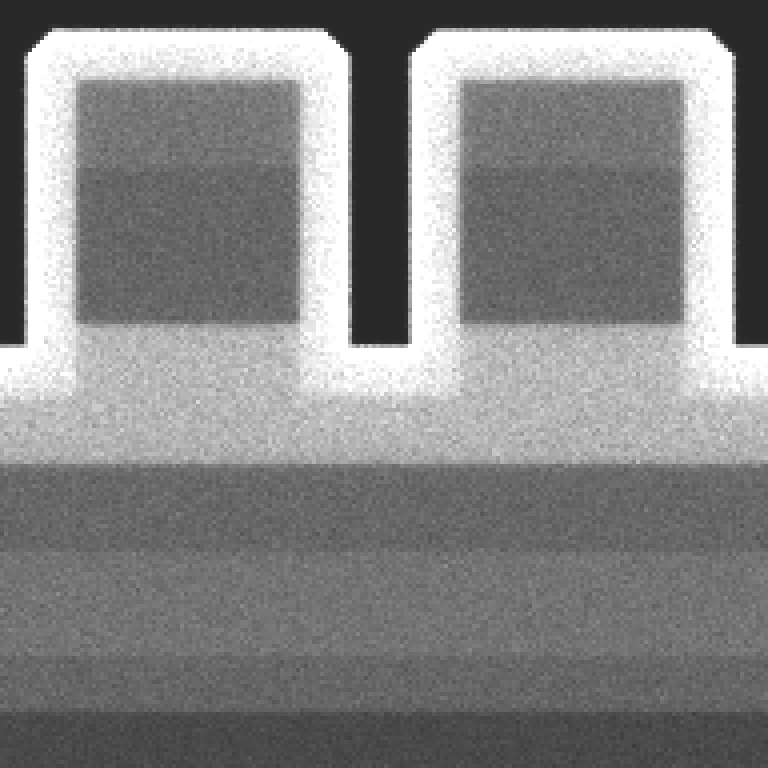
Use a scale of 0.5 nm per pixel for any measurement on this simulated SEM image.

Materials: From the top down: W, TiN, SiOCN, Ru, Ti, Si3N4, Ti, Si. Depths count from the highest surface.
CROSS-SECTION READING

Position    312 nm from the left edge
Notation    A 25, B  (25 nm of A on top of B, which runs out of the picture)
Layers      W 24, TiN 44, SiOCN 78, Ru 70, Ti 44, Si3N4 52, Ti 28, Si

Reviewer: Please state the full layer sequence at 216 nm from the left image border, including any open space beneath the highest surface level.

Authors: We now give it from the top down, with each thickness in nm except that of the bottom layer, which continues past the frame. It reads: empty 2, W 180, Ru 34, Ti 44, Si3N4 52, Ti 28, Si